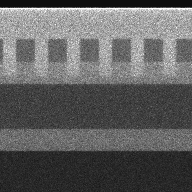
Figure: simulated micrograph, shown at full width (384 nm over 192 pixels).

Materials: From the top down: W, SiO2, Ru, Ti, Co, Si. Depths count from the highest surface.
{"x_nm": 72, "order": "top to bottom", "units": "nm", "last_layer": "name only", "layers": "W 136, Ru 16, Ti 90, Co 44, Si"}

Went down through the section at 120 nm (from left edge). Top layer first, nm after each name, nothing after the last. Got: W 62, SiO2 46, Ru 44, Ti 90, Co 44, Si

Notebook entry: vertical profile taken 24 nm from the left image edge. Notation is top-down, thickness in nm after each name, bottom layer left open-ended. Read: W 136, Ru 16, Ti 90, Co 44, Si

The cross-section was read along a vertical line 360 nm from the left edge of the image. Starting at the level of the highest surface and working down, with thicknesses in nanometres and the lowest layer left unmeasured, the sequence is W 62, SiO2 46, Ru 44, Ti 90, Co 44, Si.